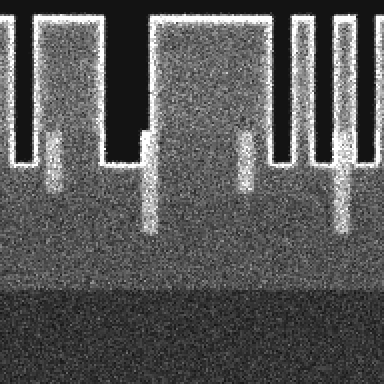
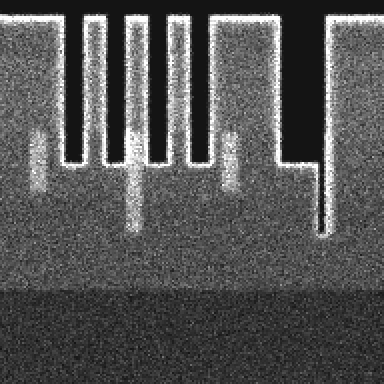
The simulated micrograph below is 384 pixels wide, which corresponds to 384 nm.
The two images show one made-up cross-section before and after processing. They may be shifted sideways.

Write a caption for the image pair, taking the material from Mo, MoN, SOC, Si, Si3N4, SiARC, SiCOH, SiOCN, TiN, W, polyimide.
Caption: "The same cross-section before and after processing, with W removed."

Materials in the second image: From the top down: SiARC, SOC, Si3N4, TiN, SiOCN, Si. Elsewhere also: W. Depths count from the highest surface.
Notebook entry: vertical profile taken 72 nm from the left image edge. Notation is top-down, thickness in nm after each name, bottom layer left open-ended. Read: empty 148, TiN 36, SiOCN 90, Si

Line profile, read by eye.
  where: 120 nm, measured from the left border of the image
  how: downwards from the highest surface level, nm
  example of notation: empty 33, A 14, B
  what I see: empty 148, TiN 36, SiOCN 90, Si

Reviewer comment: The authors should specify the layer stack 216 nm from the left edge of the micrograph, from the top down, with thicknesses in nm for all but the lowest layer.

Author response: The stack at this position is SiARC 38, SOC 78, Si3N4 32, TiN 36, SiOCN 90, Si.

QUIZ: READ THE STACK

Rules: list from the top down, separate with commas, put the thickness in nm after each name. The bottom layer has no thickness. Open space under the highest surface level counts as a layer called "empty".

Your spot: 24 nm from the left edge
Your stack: SiARC 38, SOC 78, Si3N4 32, TiN 36, SiOCN 90, Si